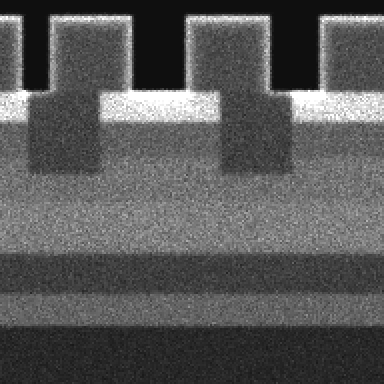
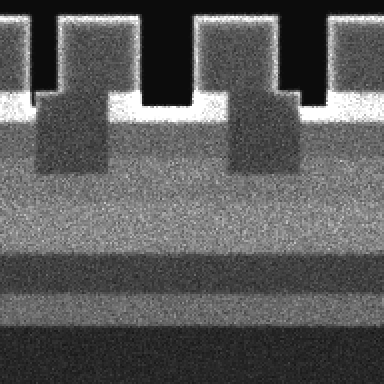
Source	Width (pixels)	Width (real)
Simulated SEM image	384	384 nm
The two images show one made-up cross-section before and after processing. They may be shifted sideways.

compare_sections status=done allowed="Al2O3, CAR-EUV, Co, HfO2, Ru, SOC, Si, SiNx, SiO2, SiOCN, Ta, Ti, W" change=removed material="HfO2"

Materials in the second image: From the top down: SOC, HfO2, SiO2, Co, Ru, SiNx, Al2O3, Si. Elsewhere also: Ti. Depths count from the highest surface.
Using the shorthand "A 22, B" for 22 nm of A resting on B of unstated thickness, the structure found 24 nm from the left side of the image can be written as SOC 76, HfO2 30, SiO2 36, Co 44, Ru 52, SiNx 40, Al2O3 32, Si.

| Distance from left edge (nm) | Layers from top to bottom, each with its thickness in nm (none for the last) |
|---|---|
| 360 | SOC 76, HfO2 30, SiO2 36, Co 44, Ru 52, SiNx 40, Al2O3 32, Si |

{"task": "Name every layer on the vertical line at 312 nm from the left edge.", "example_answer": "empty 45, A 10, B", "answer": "empty 92, HfO2 14, SiO2 36, Co 44, Ru 52, SiNx 40, Al2O3 32, Si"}